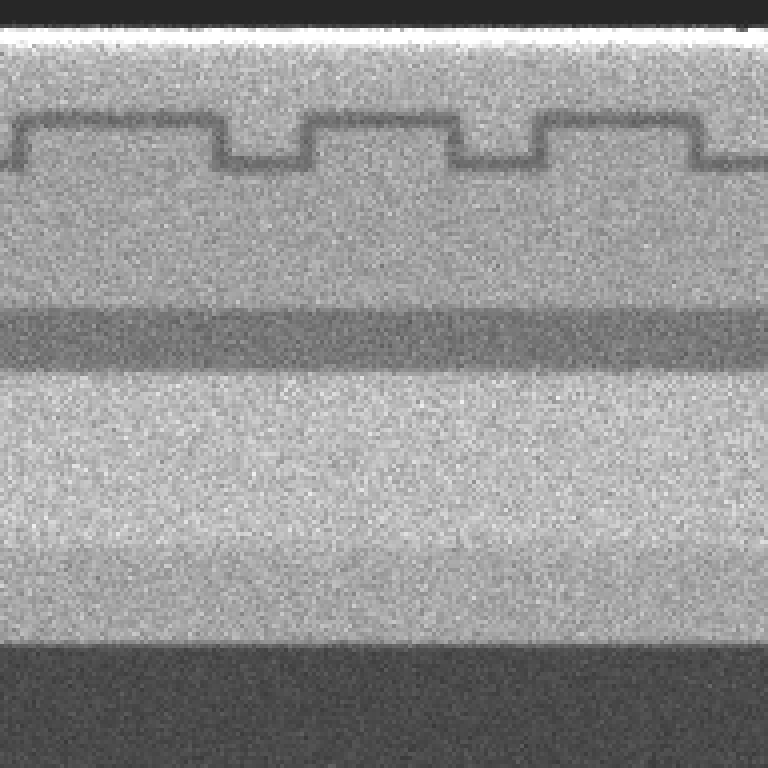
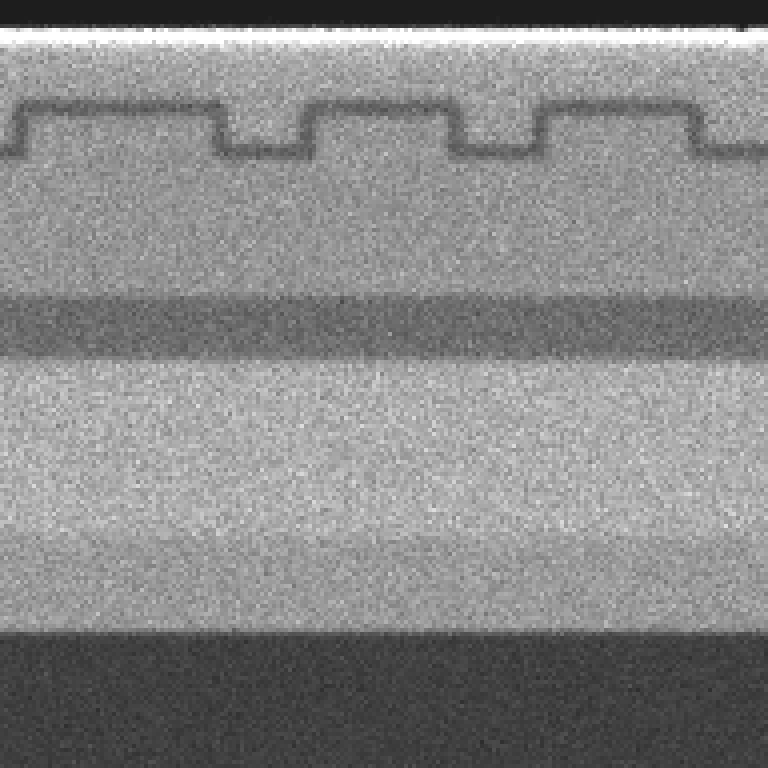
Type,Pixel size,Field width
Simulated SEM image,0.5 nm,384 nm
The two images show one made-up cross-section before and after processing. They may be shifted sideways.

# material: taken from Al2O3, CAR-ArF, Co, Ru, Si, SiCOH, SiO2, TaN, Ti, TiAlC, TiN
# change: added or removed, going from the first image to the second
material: Co
change: removed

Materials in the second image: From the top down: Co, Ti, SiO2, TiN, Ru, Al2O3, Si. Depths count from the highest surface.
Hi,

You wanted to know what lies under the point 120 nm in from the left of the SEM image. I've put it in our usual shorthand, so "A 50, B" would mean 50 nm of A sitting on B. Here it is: Co 56, Ti 8, SiO2 68, TiN 32, Ru 88, Al2O3 48, Si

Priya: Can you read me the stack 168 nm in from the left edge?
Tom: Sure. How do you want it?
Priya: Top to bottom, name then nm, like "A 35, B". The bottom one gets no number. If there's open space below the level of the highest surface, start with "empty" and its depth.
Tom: Co 34, Ti 8, SiO2 90, TiN 32, Ru 88, Al2O3 48, Si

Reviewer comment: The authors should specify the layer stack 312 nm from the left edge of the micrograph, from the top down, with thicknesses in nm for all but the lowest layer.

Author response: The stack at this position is Co 34, Ti 8, SiO2 90, TiN 32, Ru 88, Al2O3 48, Si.